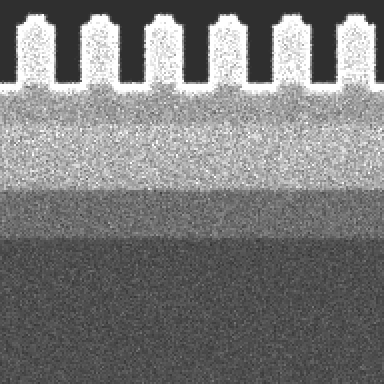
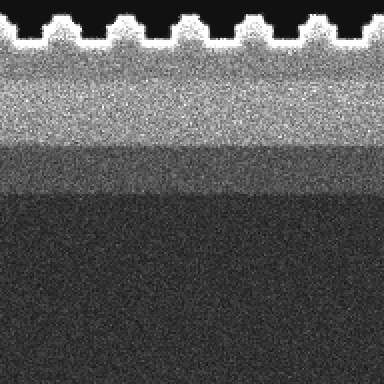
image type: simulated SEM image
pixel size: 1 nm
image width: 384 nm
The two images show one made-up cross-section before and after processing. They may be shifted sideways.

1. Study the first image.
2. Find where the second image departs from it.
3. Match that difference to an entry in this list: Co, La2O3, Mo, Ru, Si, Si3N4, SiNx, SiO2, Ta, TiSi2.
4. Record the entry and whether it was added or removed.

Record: Ru / removed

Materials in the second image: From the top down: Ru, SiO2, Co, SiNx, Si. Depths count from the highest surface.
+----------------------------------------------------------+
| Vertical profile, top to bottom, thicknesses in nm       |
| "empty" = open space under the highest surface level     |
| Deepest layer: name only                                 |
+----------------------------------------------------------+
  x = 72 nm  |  empty 8, Ru 16, SiO2 40, Co 66, SiNx 48, Si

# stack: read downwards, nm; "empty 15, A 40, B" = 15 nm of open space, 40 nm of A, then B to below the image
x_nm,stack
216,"empty 24, SiO2 40, Co 66, SiNx 48, Si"